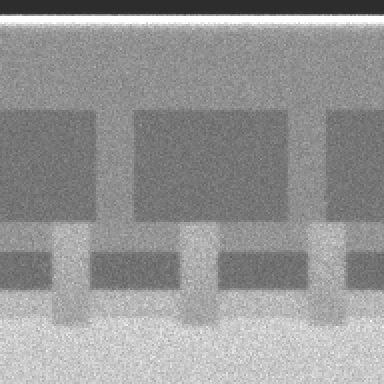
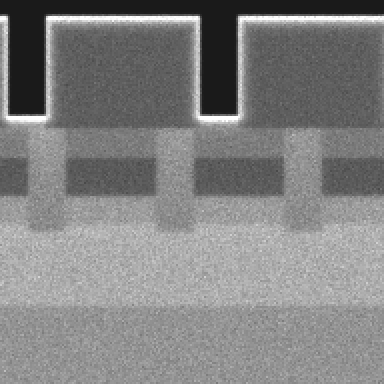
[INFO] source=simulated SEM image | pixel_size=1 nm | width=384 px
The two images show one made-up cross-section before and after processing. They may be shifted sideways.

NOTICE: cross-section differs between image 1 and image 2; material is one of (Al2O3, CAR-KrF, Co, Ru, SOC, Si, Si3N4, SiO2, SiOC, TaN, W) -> removed: SiO2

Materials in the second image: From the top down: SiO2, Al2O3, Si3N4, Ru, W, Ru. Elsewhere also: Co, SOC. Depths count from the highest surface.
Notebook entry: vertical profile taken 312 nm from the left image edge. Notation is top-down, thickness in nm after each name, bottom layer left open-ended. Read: SOC 112, Co 104, W 74, Ru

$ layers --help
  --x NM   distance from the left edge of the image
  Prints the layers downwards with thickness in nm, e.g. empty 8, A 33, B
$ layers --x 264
SOC 112, Al2O3 30, Si3N4 38, Ru 28, W 82, Ru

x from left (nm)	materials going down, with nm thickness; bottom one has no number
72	SOC 112, Al2O3 30, Si3N4 38, Ru 28, W 82, Ru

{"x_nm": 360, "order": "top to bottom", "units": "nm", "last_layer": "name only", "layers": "SOC 112, Al2O3 30, Si3N4 38, Ru 28, W 82, Ru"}